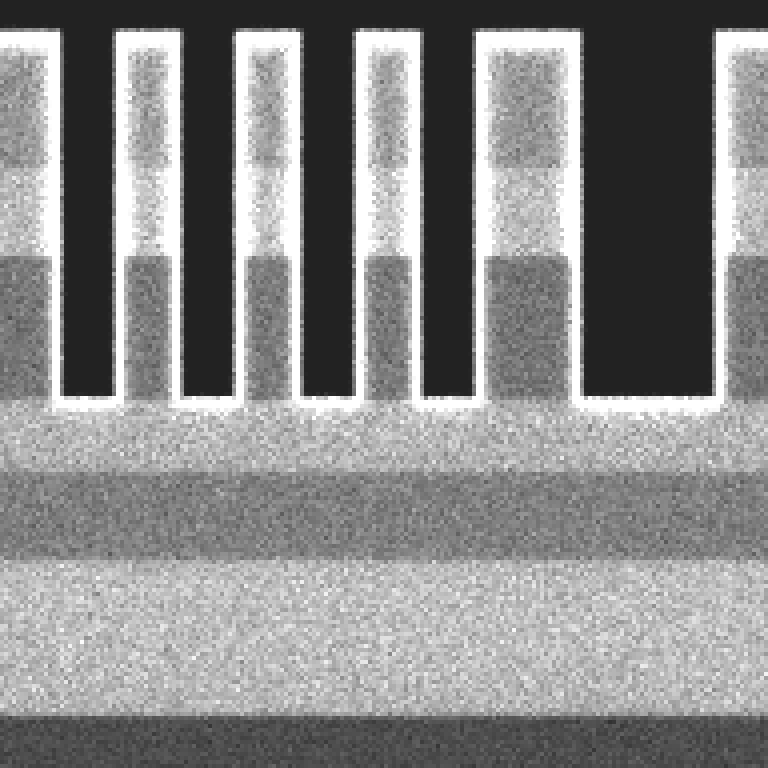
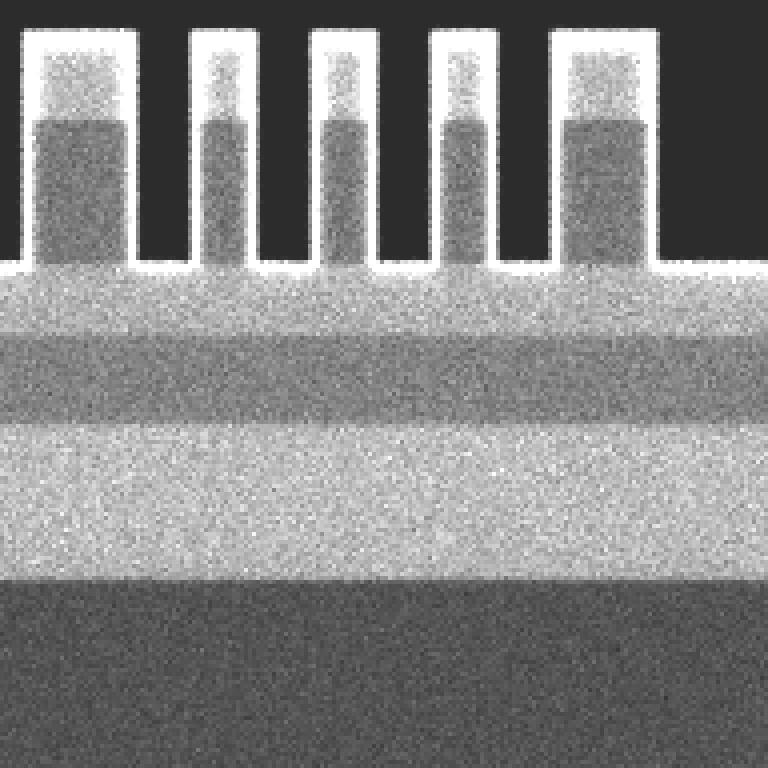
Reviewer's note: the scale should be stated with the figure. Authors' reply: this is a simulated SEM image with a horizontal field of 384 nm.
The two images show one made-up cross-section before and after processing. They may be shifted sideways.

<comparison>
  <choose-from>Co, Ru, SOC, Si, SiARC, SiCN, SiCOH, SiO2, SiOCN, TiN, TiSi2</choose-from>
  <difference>SOC removed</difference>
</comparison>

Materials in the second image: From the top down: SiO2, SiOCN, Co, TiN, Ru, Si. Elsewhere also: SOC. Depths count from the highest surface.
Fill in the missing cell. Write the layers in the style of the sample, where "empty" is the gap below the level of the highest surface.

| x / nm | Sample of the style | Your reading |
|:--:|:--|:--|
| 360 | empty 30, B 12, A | empty 116, Co 36, TiN 44, Ru 78, Si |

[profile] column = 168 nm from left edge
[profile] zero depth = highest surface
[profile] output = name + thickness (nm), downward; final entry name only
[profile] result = SiO2 44, SiOCN 72, Co 36, TiN 44, Ru 78, Si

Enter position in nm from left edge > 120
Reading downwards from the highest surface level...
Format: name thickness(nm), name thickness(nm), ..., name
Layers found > SiO2 44, SiOCN 72, Co 36, TiN 44, Ru 78, Si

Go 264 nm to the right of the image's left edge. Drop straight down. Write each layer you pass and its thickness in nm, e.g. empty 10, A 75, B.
empty 116, Co 36, TiN 44, Ru 78, Si